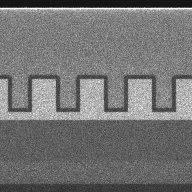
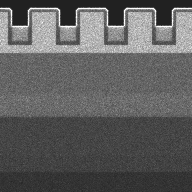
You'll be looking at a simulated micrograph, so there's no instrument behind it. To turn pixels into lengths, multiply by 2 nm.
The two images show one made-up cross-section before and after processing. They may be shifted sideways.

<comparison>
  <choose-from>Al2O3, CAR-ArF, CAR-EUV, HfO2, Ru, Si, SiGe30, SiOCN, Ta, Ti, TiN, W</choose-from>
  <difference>W removed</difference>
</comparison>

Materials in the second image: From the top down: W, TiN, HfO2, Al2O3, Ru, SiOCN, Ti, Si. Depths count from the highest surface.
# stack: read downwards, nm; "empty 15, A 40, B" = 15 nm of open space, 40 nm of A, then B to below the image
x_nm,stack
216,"empty 36, W 30, TiN 8, HfO2 16, Al2O3 82, Ru 46, SiOCN 78, Ti 32, Si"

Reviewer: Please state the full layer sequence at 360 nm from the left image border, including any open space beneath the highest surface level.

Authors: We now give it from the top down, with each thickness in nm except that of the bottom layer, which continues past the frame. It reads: TiN 8, HfO2 82, Al2O3 82, Ru 46, SiOCN 78, Ti 32, Si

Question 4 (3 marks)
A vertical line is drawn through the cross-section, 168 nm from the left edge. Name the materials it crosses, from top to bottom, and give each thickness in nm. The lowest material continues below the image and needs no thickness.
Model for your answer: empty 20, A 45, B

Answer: TiN 8, HfO2 82, Al2O3 82, Ru 46, SiOCN 78, Ti 32, Si